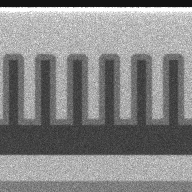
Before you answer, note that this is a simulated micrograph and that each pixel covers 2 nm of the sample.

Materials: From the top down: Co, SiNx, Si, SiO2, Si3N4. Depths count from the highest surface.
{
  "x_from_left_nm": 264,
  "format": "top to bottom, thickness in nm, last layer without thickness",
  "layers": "Co 96, SiNx 138, Si 60, SiO2 52, Si3N4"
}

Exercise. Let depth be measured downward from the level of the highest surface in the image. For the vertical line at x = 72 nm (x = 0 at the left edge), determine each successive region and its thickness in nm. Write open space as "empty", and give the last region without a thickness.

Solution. Co 96, SiNx 138, Si 60, SiO2 52, Si3N4